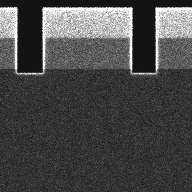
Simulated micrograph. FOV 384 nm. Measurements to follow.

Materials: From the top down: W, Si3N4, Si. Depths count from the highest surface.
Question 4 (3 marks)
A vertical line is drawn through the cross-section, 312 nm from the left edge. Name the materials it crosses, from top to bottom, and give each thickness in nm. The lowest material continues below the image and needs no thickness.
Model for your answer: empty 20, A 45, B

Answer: W 60, Si3N4 62, Si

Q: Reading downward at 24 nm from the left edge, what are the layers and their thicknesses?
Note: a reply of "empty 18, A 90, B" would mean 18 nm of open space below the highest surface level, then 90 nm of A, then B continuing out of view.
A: W 60, Si3N4 62, Si